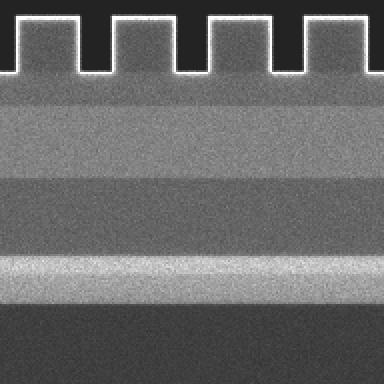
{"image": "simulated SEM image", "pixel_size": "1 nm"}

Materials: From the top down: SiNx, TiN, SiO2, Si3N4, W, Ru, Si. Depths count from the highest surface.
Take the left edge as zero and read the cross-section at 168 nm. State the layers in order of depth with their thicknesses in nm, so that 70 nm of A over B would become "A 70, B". SiNx 56, TiN 34, SiO2 72, Si3N4 78, W 18, Ru 30, Si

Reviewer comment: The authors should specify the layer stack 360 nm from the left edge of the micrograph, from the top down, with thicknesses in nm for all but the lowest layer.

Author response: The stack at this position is SiNx 56, TiN 34, SiO2 72, Si3N4 78, W 18, Ru 30, Si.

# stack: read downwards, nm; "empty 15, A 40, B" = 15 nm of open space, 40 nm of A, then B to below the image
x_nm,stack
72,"SiNx 56, TiN 34, SiO2 72, Si3N4 78, W 18, Ru 30, Si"